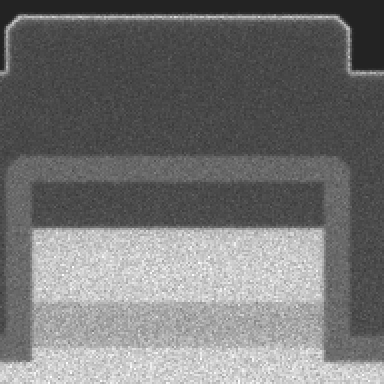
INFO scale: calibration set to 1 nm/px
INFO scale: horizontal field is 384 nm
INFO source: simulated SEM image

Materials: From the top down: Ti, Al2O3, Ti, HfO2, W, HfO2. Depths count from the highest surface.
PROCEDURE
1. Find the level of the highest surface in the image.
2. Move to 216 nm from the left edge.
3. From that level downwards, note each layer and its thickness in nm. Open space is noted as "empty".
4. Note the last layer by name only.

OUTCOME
Ti 140, Al2O3 26, Ti 46, HfO2 74, W 46, HfO2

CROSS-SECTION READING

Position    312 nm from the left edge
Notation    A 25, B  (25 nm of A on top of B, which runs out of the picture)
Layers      Ti 140, Al2O3 26, Ti 46, HfO2 74, W 46, HfO2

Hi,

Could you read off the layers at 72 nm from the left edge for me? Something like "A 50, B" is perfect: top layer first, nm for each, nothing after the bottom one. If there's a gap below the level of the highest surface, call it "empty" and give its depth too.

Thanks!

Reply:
Ti 140, Al2O3 26, Ti 46, HfO2 74, W 46, HfO2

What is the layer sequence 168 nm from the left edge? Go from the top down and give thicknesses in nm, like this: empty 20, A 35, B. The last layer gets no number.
Ti 140, Al2O3 26, Ti 46, HfO2 74, W 46, HfO2